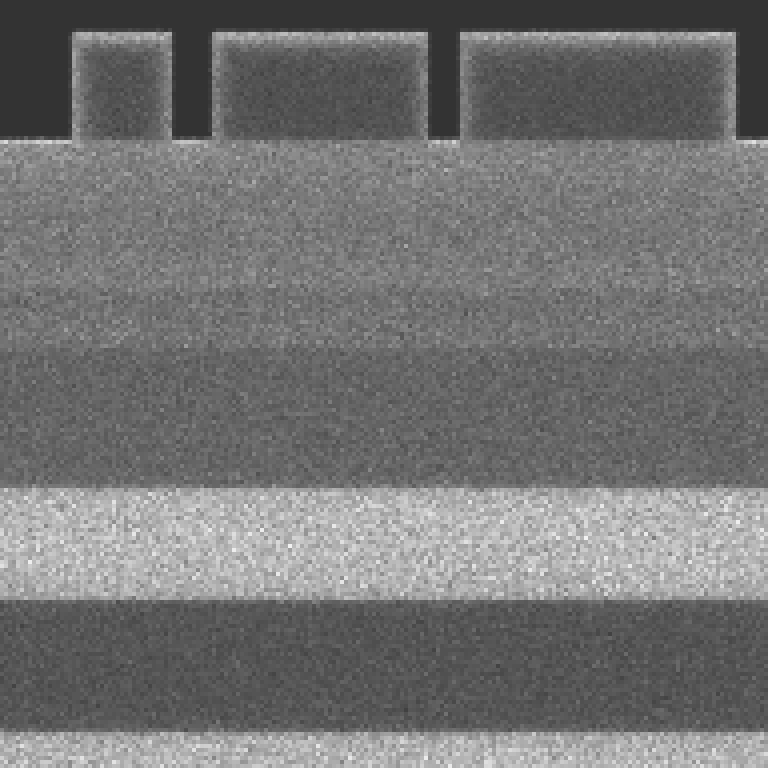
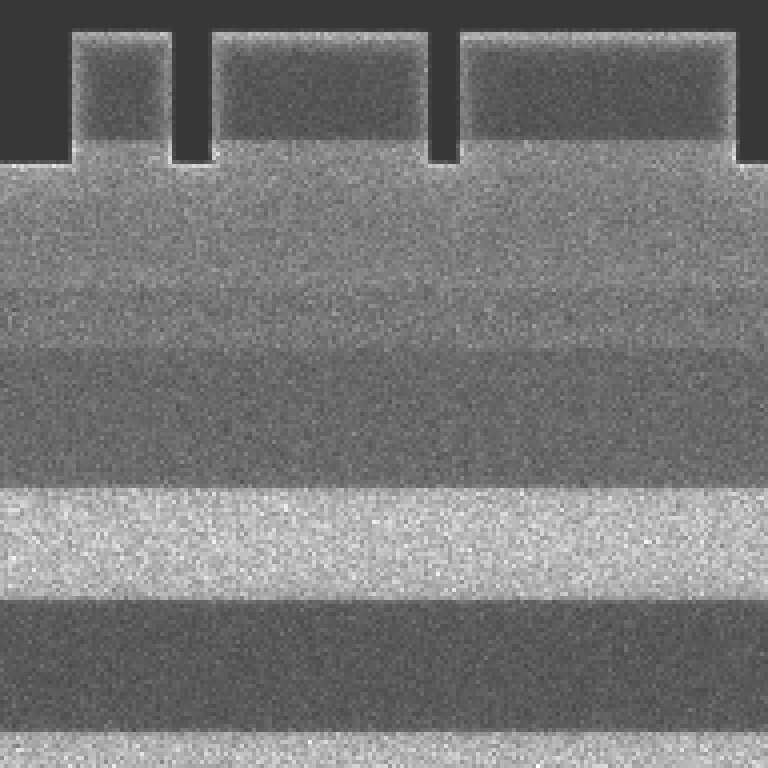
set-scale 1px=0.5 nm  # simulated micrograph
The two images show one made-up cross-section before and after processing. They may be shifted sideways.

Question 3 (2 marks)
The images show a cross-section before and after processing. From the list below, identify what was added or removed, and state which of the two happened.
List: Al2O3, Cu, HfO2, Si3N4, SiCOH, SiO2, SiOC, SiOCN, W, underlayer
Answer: W was removed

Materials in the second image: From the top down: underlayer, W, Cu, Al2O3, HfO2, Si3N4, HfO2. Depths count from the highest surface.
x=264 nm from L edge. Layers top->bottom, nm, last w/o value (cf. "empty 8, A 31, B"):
underlayer 54, W 74, Cu 30, Al2O3 70, HfO2 56, Si3N4 66, HfO2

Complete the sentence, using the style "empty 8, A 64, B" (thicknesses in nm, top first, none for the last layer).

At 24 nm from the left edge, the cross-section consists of empty 66, W 62, Cu 30, Al2O3 70, HfO2 56, Si3N4 66, HfO2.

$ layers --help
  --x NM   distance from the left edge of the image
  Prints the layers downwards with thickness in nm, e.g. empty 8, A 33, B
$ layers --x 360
underlayer 54, W 74, Cu 30, Al2O3 70, HfO2 56, Si3N4 66, HfO2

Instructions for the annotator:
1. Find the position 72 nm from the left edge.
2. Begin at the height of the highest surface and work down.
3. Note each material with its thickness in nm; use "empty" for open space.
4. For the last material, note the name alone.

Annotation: underlayer 54, W 74, Cu 30, Al2O3 70, HfO2 56, Si3N4 66, HfO2